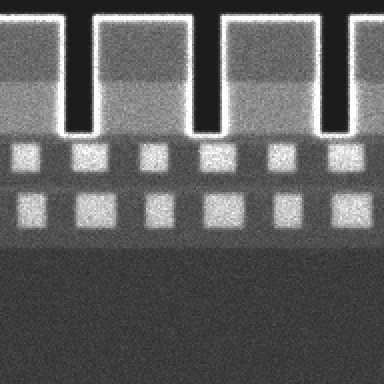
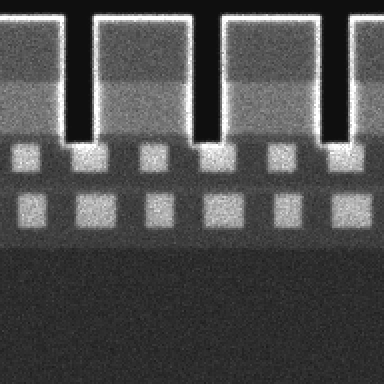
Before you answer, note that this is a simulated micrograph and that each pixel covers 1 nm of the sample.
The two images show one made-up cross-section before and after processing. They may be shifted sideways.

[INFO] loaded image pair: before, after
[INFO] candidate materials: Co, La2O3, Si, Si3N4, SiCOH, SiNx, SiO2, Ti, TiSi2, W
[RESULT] removed SiNx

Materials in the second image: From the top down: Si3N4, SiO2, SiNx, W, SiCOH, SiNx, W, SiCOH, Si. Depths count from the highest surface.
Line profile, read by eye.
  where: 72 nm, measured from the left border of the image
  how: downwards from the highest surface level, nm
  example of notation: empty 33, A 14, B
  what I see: empty 128, W 28, SiCOH 14, SiNx 8, SiCOH 54, Si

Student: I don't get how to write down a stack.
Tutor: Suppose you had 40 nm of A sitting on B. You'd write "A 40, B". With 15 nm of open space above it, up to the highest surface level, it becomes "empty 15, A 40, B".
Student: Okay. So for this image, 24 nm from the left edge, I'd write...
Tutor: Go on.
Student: Si3N4 66, SiO2 52, SiNx 10, W 28, SiCOH 14, SiNx 8, W 34, SiCOH 20, Si